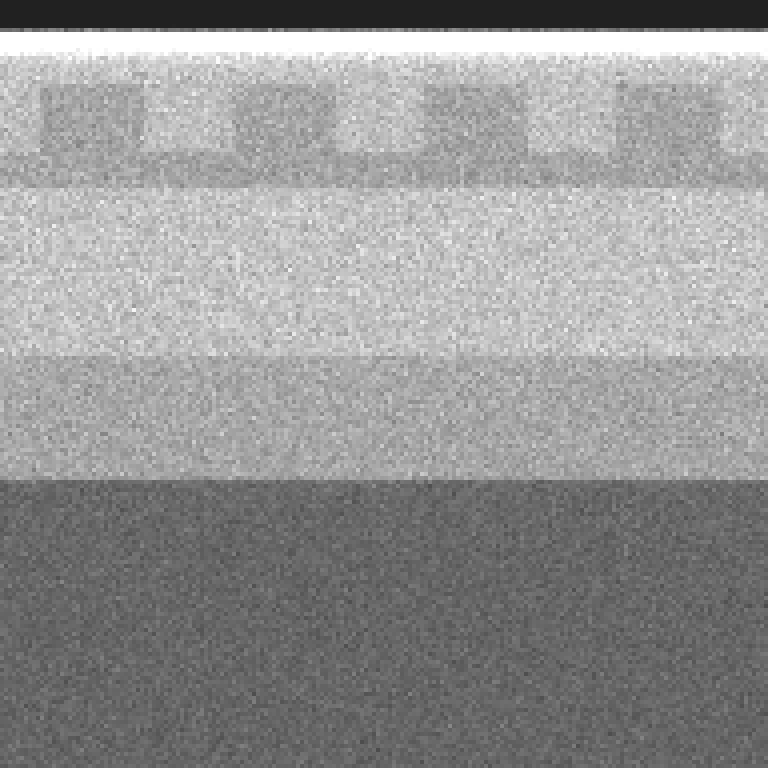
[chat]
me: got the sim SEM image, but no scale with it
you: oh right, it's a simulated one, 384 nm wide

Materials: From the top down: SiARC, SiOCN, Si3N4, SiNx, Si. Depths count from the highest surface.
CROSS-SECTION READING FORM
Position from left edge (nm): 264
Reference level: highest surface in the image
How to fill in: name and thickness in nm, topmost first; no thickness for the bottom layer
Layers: SiARC 60, SiOCN 18, Si3N4 84, SiNx 62, Si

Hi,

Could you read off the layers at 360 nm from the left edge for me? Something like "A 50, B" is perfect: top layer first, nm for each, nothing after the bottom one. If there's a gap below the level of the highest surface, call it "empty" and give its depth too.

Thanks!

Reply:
SiARC 60, SiOCN 18, Si3N4 84, SiNx 62, Si